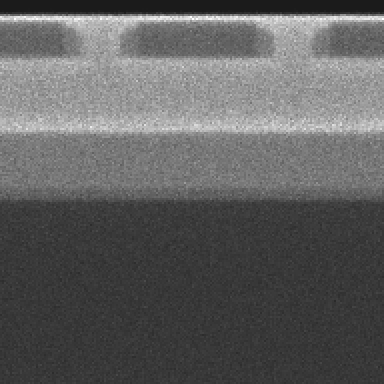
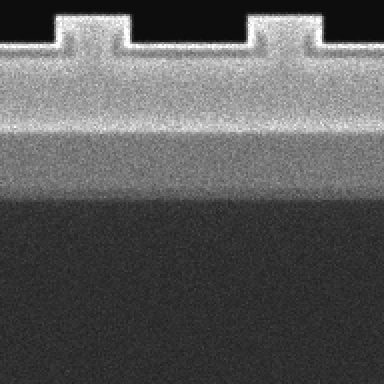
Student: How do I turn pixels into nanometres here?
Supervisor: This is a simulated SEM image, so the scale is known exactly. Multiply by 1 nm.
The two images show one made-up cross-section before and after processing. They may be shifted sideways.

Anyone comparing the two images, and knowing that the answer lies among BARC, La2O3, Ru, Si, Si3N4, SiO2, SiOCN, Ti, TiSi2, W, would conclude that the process removed Si3N4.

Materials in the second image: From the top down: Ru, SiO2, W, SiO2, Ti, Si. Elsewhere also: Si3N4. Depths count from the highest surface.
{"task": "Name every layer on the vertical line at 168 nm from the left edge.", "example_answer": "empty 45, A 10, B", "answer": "empty 28, Si3N4 14, W 74, SiO2 56, Ti 12, Si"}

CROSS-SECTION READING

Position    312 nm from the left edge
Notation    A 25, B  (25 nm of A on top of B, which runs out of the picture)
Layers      Ru 12, SiO2 30, W 74, SiO2 56, Ti 12, Si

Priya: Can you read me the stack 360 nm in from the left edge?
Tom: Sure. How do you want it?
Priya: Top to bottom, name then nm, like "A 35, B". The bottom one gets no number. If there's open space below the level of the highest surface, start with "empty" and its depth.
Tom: empty 28, Si3N4 14, W 74, SiO2 56, Ti 12, Si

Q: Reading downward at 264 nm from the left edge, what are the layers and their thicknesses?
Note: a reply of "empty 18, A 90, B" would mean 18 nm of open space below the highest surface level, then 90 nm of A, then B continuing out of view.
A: Ru 20, SiO2 22, W 74, SiO2 56, Ti 12, Si